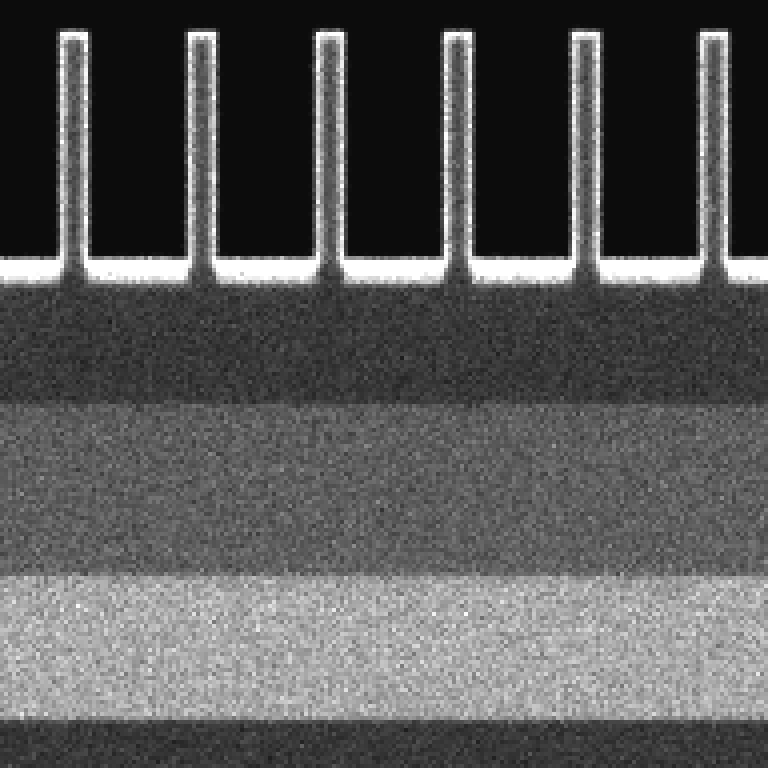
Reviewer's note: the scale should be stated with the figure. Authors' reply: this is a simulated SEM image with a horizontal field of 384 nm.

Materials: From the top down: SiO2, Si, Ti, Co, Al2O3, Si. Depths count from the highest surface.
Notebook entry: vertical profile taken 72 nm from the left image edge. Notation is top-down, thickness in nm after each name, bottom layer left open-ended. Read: empty 114, SiO2 12, Si 60, Ti 86, Co 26, Al2O3 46, Si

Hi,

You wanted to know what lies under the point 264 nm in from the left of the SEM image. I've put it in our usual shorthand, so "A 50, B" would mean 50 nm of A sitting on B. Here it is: empty 114, SiO2 12, Si 60, Ti 86, Co 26, Al2O3 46, Si